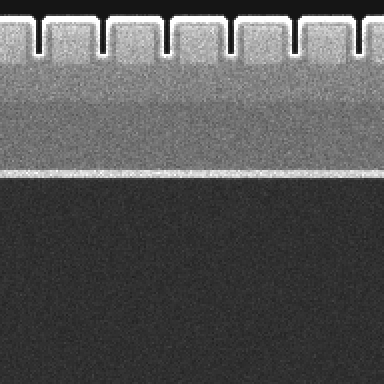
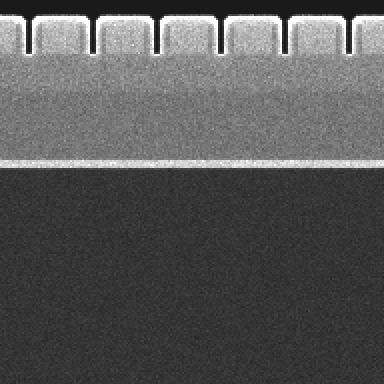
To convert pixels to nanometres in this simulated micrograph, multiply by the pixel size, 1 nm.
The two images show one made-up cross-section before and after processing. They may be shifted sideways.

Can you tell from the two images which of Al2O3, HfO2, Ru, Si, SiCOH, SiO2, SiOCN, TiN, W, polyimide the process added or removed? Yes, it removed Al2O3.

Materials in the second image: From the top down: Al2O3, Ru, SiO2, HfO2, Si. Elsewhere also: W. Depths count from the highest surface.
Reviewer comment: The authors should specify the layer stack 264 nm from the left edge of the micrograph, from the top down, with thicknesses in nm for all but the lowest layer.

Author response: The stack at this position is W 38, Ru 38, SiO2 68, HfO2 8, Si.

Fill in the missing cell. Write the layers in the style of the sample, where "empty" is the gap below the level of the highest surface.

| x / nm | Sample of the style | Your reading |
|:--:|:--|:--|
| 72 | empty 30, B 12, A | W 38, Ru 38, SiO2 68, HfO2 8, Si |